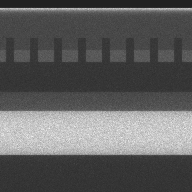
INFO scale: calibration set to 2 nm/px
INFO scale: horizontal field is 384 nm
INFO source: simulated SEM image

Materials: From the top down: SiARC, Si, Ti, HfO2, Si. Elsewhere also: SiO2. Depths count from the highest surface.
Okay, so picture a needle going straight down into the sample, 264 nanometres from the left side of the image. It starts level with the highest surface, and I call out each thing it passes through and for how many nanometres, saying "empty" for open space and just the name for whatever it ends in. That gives SiARC 60, Si 108, Ti 38, HfO2 88, Si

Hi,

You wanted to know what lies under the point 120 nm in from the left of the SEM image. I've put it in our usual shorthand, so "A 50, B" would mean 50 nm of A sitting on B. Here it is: SiARC 60, Si 108, Ti 38, HfO2 88, Si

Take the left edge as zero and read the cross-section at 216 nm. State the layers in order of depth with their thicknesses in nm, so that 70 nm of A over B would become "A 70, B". SiARC 60, Si 108, Ti 38, HfO2 88, Si